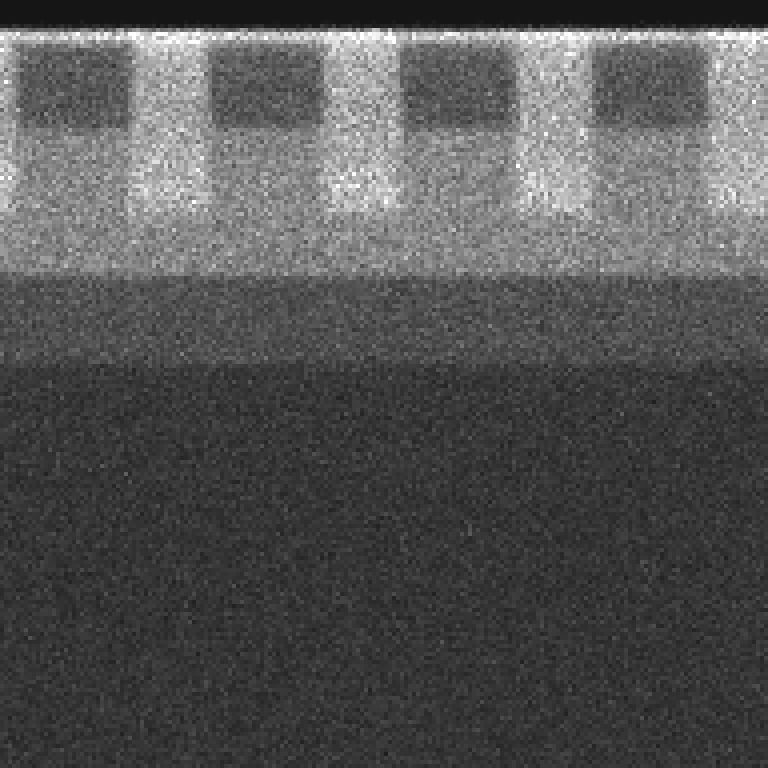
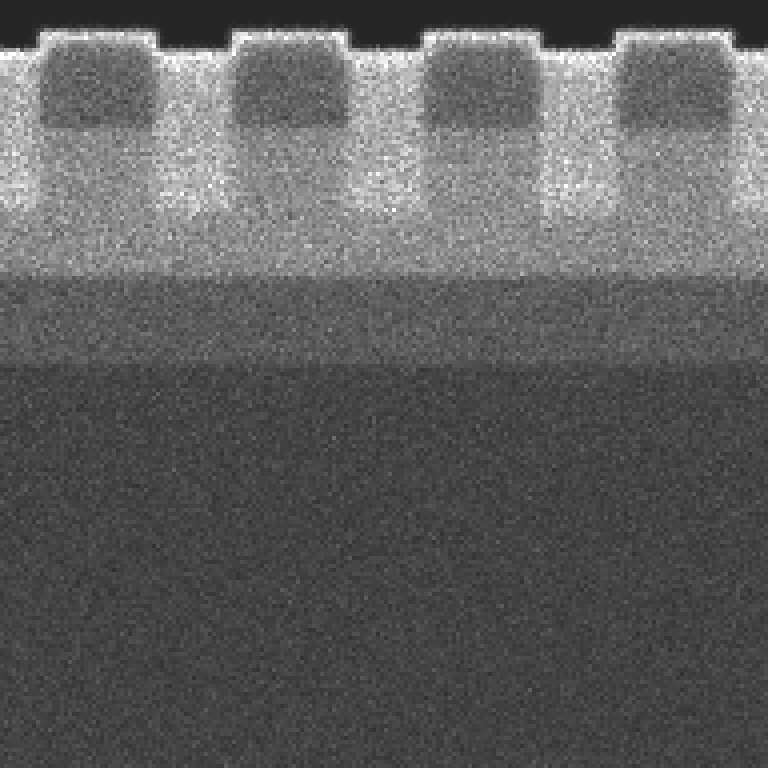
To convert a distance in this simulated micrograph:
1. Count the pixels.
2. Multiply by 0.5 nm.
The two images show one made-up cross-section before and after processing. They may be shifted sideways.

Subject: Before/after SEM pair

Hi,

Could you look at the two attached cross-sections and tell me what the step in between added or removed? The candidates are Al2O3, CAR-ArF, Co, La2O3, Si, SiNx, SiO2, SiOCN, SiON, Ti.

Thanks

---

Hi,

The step removed Co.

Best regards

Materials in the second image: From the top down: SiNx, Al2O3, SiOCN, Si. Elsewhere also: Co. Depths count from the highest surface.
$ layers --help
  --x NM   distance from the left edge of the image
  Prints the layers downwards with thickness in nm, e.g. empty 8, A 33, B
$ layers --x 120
SiNx 48, Al2O3 74, SiOCN 44, Si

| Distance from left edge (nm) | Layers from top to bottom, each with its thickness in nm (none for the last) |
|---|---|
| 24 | SiNx 48, Al2O3 74, SiOCN 44, Si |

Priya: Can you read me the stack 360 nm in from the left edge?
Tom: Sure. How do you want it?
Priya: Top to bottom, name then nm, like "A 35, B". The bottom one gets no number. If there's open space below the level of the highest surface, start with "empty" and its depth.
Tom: SiNx 48, Al2O3 74, SiOCN 44, Si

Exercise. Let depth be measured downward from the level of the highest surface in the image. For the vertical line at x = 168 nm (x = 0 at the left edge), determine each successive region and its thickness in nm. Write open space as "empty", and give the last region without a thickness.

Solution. SiNx 48, Al2O3 74, SiOCN 44, Si